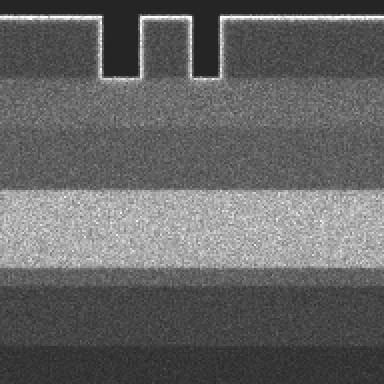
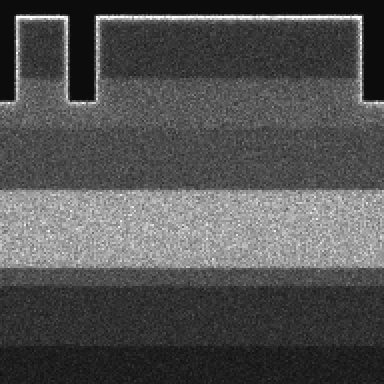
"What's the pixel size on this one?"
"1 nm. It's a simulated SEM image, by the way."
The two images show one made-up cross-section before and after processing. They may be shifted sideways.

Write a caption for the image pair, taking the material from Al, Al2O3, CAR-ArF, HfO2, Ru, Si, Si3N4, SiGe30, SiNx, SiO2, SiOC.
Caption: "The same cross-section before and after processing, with Ru removed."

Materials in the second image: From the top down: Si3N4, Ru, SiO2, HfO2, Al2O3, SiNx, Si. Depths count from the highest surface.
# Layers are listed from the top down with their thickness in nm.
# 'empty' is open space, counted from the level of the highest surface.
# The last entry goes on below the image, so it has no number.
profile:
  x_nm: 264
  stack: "Si3N4 62, Ru 50, SiO2 62, HfO2 78, Al2O3 18, SiNx 60, Si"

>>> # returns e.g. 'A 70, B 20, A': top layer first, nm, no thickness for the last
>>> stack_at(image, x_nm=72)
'empty 86, Ru 26, SiO2 62, HfO2 78, Al2O3 18, SiNx 60, Si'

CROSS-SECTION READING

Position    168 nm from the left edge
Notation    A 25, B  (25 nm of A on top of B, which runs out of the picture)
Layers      Si3N4 62, Ru 50, SiO2 62, HfO2 78, Al2O3 18, SiNx 60, Si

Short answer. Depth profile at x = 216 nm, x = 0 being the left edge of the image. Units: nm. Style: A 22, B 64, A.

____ Si3N4 62, Ru 50, SiO2 62, HfO2 78, Al2O3 18, SiNx 60, Si